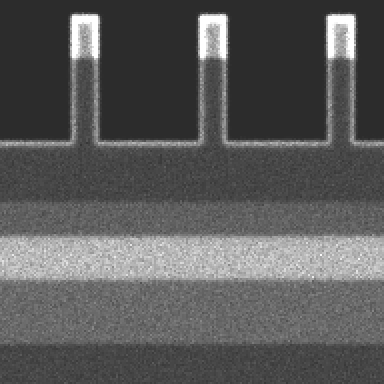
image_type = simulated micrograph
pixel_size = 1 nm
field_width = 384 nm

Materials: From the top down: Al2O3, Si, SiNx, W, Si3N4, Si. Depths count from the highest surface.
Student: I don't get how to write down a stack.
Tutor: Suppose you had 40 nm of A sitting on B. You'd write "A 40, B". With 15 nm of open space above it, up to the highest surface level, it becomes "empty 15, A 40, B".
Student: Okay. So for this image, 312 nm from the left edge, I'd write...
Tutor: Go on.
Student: empty 126, Si 60, SiNx 34, W 44, Si3N4 64, Si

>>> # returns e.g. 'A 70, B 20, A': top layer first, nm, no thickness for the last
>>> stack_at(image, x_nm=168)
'empty 126, Si 60, SiNx 34, W 44, Si3N4 64, Si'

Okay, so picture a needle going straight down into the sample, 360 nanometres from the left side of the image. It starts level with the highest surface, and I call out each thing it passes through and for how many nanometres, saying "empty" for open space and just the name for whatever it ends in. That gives empty 126, Si 60, SiNx 34, W 44, Si3N4 64, Si